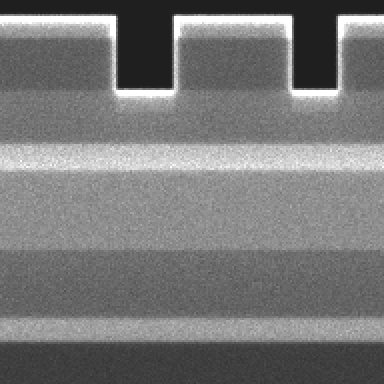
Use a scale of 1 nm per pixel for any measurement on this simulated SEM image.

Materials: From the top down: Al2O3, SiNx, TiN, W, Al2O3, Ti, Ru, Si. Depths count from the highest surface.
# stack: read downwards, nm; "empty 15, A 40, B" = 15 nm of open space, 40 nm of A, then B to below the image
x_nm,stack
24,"Al2O3 22, SiNx 52, TiN 54, W 26, Al2O3 80, Ti 68, Ru 24, Si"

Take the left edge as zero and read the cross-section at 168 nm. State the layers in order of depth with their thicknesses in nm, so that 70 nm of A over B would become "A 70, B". empty 74, Al2O3 22, TiN 32, W 26, Al2O3 80, Ti 68, Ru 24, Si